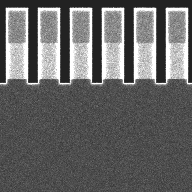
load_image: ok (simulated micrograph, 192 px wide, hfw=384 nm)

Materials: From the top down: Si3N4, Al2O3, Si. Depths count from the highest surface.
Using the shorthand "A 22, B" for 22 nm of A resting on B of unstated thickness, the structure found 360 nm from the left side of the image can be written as Si3N4 70, Al2O3 72, Si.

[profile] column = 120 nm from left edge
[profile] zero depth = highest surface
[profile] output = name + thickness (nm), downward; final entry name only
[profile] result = empty 150, Si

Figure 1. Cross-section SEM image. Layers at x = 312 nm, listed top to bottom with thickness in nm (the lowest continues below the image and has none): empty 150, Si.